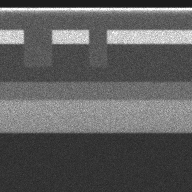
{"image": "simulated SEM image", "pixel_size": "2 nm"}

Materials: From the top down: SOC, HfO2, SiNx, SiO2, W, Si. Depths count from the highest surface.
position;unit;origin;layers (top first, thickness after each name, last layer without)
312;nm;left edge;SOC 44, HfO2 28, SiNx 76, SiO2 36, W 66, Si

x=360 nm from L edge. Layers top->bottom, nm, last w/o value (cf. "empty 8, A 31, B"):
SOC 44, HfO2 28, SiNx 76, SiO2 36, W 66, Si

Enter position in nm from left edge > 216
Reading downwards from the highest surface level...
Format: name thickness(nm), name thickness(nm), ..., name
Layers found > SOC 44, HfO2 28, SiNx 76, SiO2 36, W 66, Si